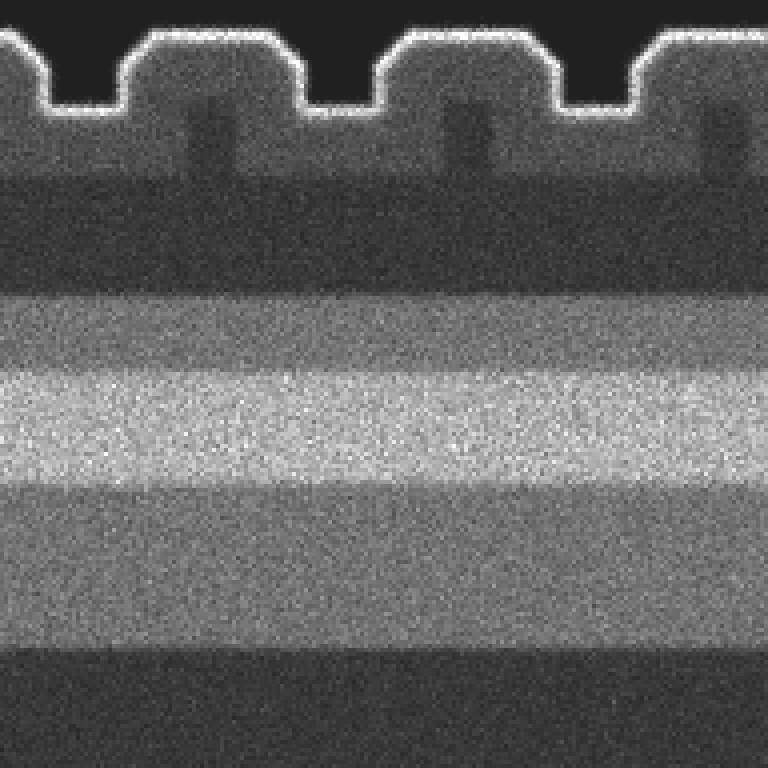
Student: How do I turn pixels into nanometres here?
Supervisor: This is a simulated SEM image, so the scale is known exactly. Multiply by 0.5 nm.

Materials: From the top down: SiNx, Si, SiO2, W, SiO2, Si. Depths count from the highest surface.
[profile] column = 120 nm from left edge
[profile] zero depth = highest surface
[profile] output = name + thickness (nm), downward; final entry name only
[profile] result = SiNx 72, Si 60, SiO2 38, W 56, SiO2 82, Si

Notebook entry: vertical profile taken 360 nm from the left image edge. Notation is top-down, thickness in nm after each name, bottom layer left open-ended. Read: SiNx 34, Si 98, SiO2 38, W 56, SiO2 82, Si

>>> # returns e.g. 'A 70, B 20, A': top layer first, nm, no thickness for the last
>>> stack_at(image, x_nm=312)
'empty 38, SiNx 34, Si 60, SiO2 38, W 56, SiO2 82, Si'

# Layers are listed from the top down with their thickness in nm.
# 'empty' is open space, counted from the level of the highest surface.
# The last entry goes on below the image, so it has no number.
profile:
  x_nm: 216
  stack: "SiNx 72, Si 60, SiO2 38, W 56, SiO2 82, Si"